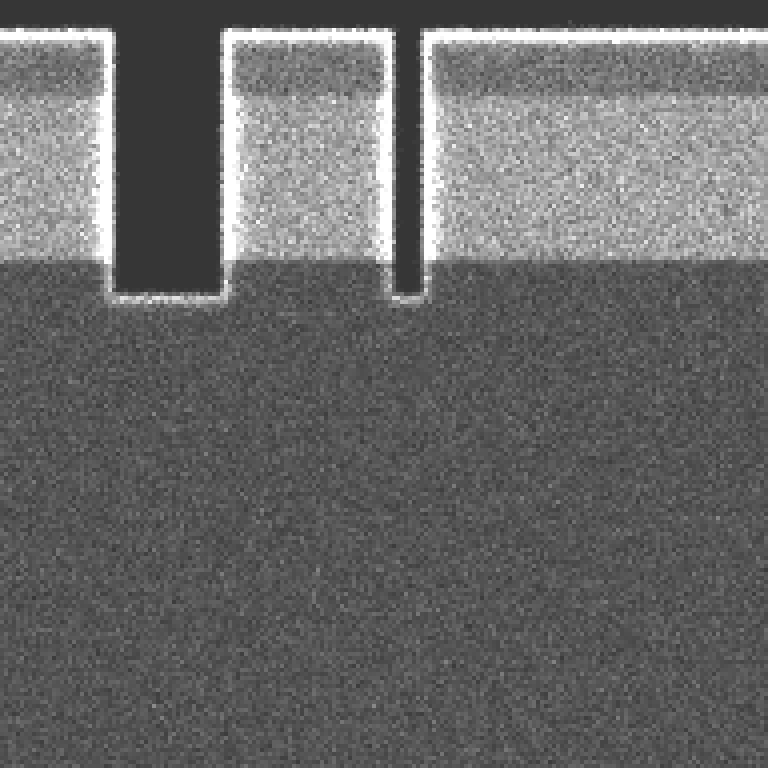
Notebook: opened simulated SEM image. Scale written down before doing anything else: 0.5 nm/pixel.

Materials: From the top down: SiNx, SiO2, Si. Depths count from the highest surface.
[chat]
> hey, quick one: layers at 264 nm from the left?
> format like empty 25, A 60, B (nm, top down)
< SiNx 32, SiO2 82, Si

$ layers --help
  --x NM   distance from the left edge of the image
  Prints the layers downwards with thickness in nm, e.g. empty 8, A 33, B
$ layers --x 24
SiNx 32, SiO2 82, Si